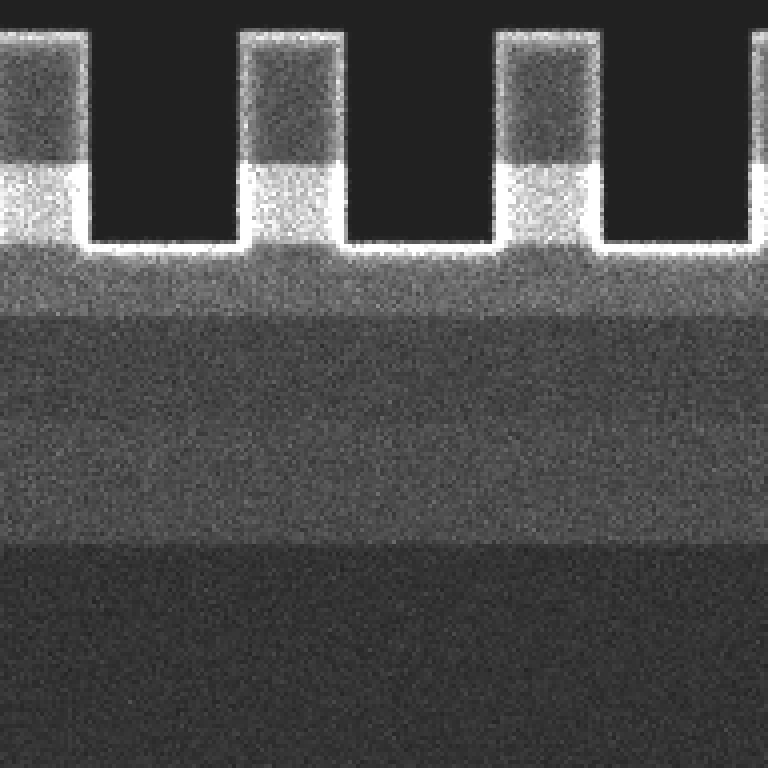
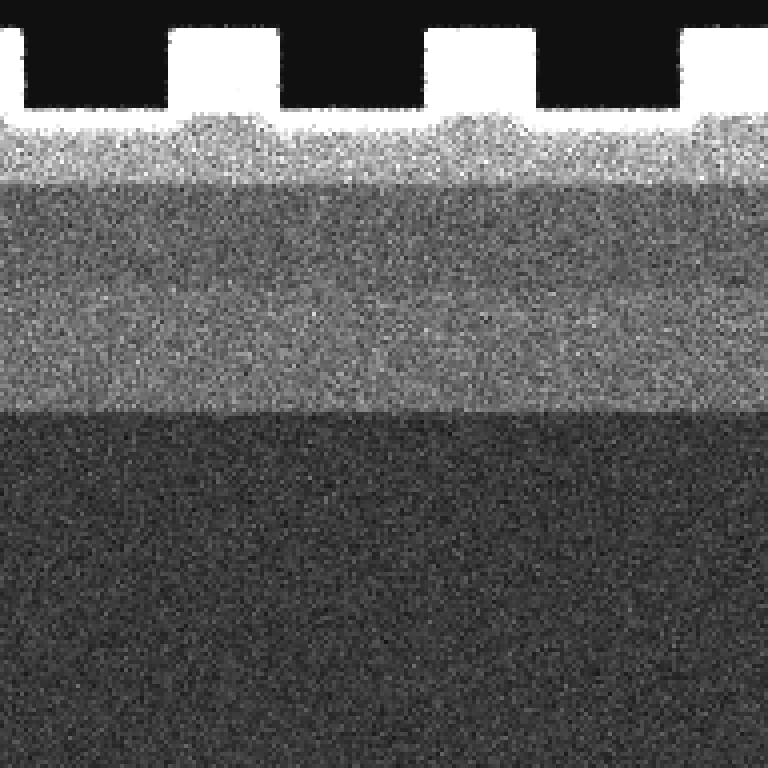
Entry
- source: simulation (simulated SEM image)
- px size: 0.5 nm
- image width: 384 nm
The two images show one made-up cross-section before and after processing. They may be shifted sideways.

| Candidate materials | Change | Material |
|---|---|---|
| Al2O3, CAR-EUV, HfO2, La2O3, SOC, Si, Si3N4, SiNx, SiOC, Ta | removed | SOC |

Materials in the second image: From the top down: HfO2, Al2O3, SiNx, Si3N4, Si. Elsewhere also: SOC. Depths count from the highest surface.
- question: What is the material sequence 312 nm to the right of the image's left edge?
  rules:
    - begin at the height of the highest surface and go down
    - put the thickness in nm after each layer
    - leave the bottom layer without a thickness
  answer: empty 40, Al2O3 36, SiNx 52, Si3N4 62, Si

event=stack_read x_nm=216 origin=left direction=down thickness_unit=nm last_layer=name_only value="HfO2 40, Al2O3 36, SiNx 52, Si3N4 62, Si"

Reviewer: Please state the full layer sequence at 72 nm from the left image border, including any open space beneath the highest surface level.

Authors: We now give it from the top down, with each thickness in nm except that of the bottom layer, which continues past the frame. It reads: empty 40, Al2O3 36, SiNx 52, Si3N4 62, Si